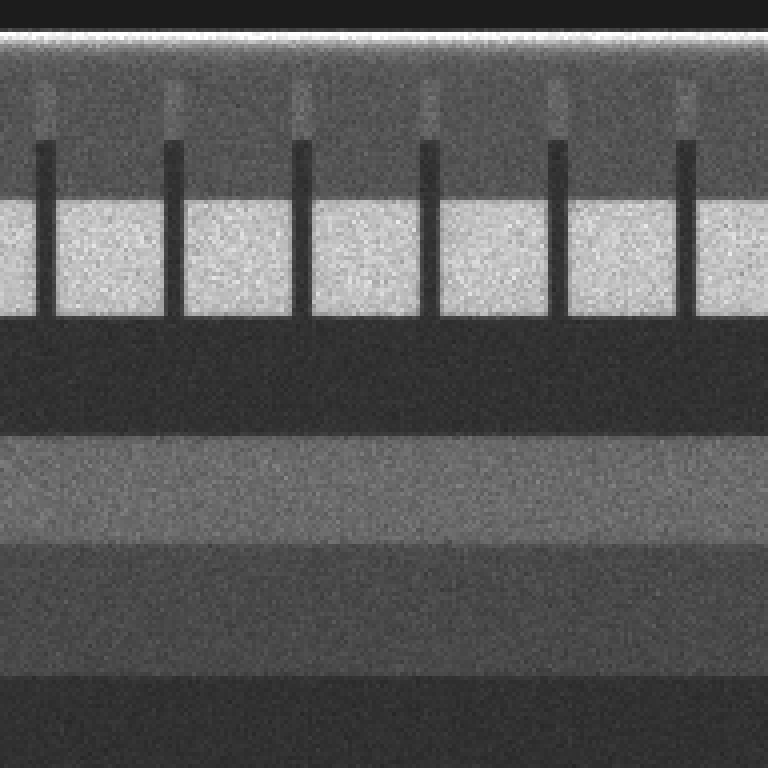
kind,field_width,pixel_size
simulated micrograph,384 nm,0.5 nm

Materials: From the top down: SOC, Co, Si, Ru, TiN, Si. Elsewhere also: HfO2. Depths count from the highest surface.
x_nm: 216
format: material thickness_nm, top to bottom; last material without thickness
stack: SOC 24, Co 30, Si 148, Ru 54, TiN 66, Si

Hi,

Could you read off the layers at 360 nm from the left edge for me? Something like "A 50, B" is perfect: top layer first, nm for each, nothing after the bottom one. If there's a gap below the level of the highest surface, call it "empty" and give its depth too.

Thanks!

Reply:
SOC 84, HfO2 58, Si 60, Ru 54, TiN 66, Si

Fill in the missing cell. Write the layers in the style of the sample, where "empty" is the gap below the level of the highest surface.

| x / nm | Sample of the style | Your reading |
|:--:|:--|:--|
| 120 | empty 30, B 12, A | SOC 84, HfO2 58, Si 60, Ru 54, TiN 66, Si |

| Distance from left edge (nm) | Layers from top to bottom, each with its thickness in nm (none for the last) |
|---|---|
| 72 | SOC 84, HfO2 58, Si 60, Ru 54, TiN 66, Si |